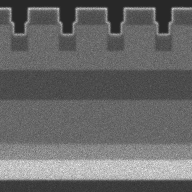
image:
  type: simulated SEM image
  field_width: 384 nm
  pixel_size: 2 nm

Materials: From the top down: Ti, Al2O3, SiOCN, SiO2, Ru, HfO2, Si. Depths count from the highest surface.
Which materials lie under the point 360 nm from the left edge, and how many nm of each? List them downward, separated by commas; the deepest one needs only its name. Ti 34, Al2O3 90, SiOCN 60, SiO2 88, Ru 32, HfO2 40, Si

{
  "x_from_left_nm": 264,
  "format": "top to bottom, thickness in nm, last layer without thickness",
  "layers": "Ti 34, Al2O3 90, SiOCN 60, SiO2 88, Ru 32, HfO2 40, Si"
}